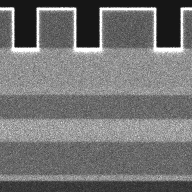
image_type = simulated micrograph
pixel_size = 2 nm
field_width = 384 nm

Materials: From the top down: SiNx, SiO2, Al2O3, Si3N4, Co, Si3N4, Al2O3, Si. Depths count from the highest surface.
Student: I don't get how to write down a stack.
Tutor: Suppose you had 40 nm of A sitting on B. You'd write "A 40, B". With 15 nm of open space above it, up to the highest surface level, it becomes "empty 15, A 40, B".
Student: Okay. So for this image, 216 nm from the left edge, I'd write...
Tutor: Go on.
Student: SiNx 80, SiO2 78, Al2O3 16, Si3N4 48, Co 46, Si3N4 66, Al2O3 12, Si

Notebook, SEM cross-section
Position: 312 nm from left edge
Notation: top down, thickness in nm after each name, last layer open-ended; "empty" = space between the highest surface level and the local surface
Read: empty 80, SiO2 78, Al2O3 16, Si3N4 48, Co 46, Si3N4 66, Al2O3 12, Si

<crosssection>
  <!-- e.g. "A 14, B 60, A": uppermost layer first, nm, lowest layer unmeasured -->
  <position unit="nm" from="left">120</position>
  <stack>SiNx 80, SiO2 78, Al2O3 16, Si3N4 48, Co 46, Si3N4 66, Al2O3 12, Si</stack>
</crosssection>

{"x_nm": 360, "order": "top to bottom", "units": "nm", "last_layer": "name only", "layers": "empty 80, SiO2 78, Al2O3 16, Si3N4 48, Co 46, Si3N4 66, Al2O3 12, Si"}